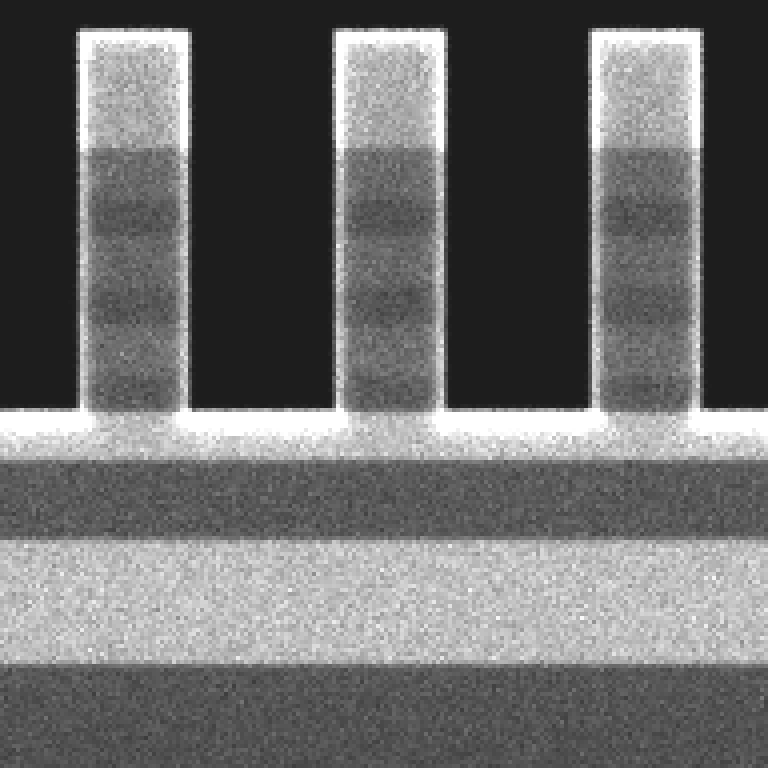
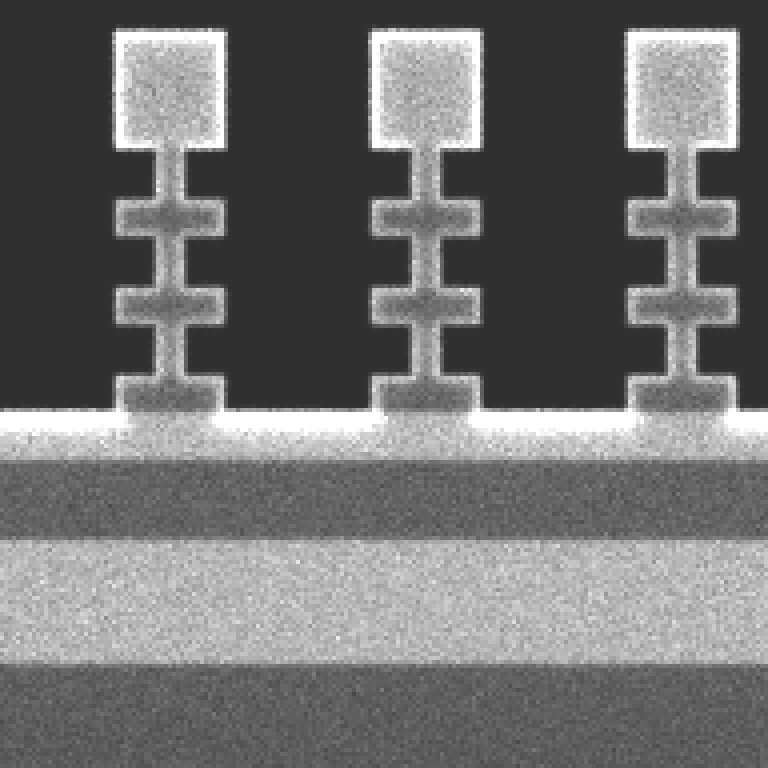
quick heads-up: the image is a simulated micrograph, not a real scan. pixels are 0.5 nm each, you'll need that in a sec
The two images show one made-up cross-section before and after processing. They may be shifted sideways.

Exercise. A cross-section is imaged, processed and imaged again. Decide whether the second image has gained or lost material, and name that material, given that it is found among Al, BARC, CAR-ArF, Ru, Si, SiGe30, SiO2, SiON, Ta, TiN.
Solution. removed: SiGe30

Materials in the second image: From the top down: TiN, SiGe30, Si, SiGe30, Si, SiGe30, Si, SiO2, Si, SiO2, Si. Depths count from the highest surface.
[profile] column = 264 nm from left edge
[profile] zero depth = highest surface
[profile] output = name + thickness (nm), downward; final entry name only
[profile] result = empty 190, SiO2 24, Si 40, SiO2 62, Si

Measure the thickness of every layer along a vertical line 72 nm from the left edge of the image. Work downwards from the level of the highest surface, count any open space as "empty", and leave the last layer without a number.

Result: TiN 58, empty 26, Si 18, empty 26, Si 18, empty 26, Si 18, SiO2 24, Si 40, SiO2 62, Si